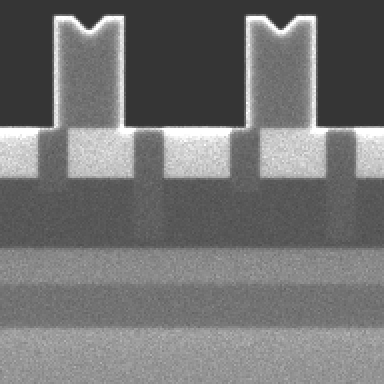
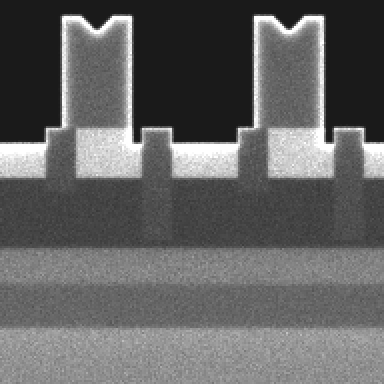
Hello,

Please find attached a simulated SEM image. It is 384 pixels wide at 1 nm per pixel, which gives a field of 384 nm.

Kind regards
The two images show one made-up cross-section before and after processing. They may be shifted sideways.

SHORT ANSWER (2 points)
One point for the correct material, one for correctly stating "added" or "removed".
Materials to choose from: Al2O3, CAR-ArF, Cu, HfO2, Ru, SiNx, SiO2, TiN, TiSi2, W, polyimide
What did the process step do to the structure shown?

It removed HfO2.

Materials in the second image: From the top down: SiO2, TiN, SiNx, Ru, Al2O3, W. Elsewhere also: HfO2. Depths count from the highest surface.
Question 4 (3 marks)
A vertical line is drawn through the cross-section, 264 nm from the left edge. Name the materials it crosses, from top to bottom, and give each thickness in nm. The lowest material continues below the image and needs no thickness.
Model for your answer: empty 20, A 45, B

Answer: SiO2 112, TiN 64, SiNx 56, Ru 36, Al2O3 44, W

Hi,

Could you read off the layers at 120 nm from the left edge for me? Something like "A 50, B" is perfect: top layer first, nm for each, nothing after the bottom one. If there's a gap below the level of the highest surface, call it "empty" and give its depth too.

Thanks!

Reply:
SiO2 112, HfO2 50, SiNx 70, Ru 36, Al2O3 44, W